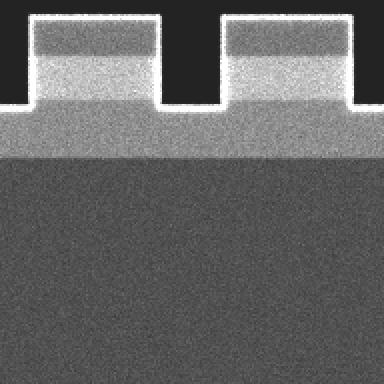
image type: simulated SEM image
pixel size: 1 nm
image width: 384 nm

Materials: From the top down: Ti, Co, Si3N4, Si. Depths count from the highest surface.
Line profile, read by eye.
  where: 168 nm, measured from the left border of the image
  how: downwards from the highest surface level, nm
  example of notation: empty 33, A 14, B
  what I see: empty 90, Si3N4 52, Si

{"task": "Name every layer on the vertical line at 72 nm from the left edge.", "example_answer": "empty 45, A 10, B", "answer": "Ti 40, Co 44, Si3N4 58, Si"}